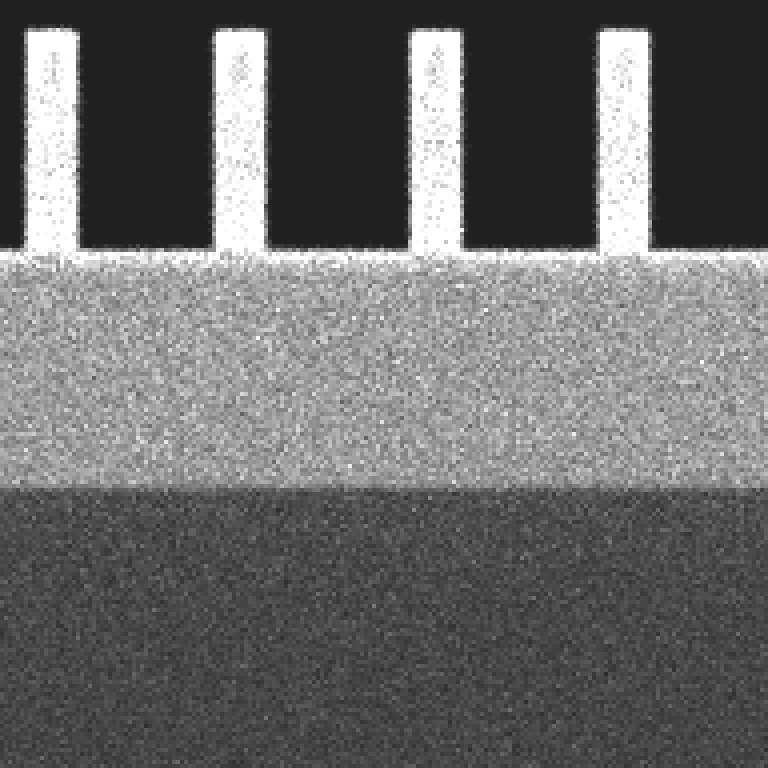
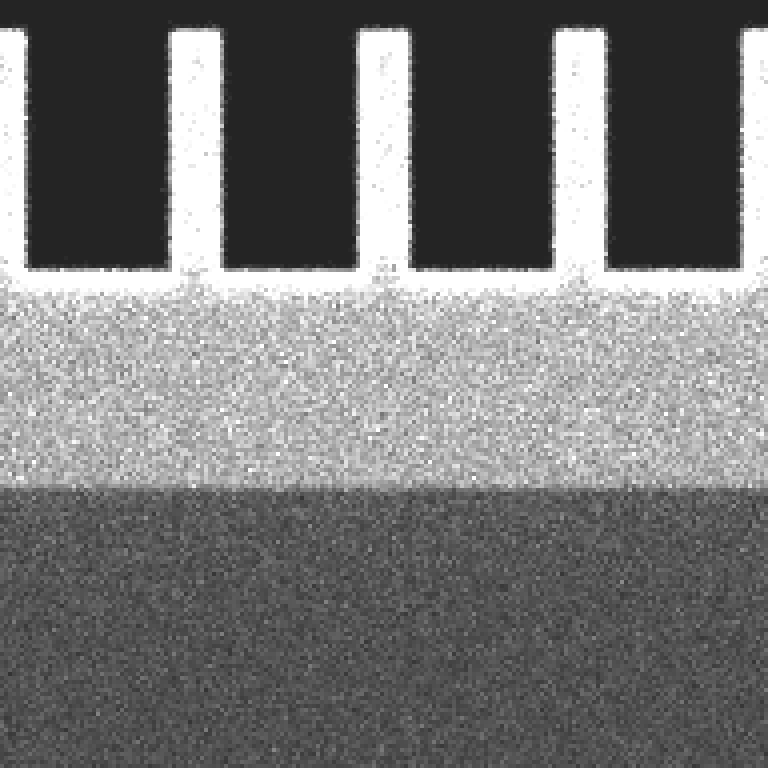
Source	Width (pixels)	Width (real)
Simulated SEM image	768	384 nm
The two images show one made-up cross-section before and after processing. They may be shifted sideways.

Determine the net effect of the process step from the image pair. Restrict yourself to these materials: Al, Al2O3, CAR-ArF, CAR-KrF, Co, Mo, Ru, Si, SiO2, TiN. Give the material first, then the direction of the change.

TiN: removed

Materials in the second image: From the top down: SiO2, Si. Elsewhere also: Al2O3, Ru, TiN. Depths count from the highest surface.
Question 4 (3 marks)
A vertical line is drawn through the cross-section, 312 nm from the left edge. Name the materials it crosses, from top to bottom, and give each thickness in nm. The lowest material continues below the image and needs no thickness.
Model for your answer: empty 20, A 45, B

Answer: empty 120, SiO2 108, Si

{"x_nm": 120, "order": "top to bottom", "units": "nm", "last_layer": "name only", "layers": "empty 120, SiO2 108, Si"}